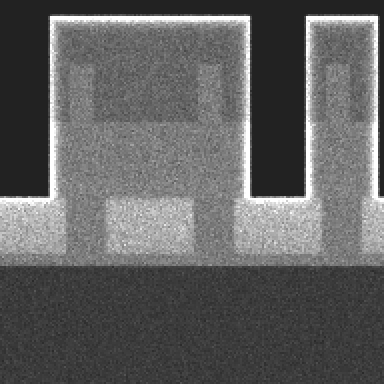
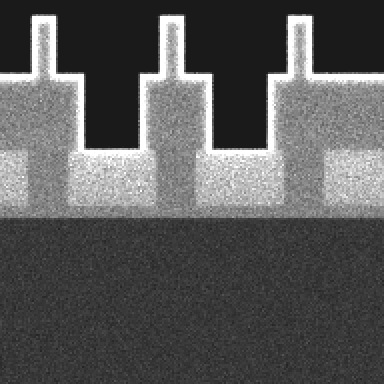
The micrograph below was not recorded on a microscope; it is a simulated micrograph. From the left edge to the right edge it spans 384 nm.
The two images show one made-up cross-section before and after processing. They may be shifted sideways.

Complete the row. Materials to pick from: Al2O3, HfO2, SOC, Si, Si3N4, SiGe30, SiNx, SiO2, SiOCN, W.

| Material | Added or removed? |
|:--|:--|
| SOC | removed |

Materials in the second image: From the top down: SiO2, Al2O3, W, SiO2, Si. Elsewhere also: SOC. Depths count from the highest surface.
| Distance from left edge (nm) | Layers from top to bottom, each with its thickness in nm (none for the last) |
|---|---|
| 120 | empty 134, W 56, SiO2 12, Si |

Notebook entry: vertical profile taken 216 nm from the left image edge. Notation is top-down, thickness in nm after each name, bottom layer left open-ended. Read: empty 134, W 56, SiO2 12, Si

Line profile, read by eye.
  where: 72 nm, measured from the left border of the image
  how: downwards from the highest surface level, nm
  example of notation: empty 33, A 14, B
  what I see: empty 58, SiO2 56, Al2O3 20, W 56, SiO2 12, Si